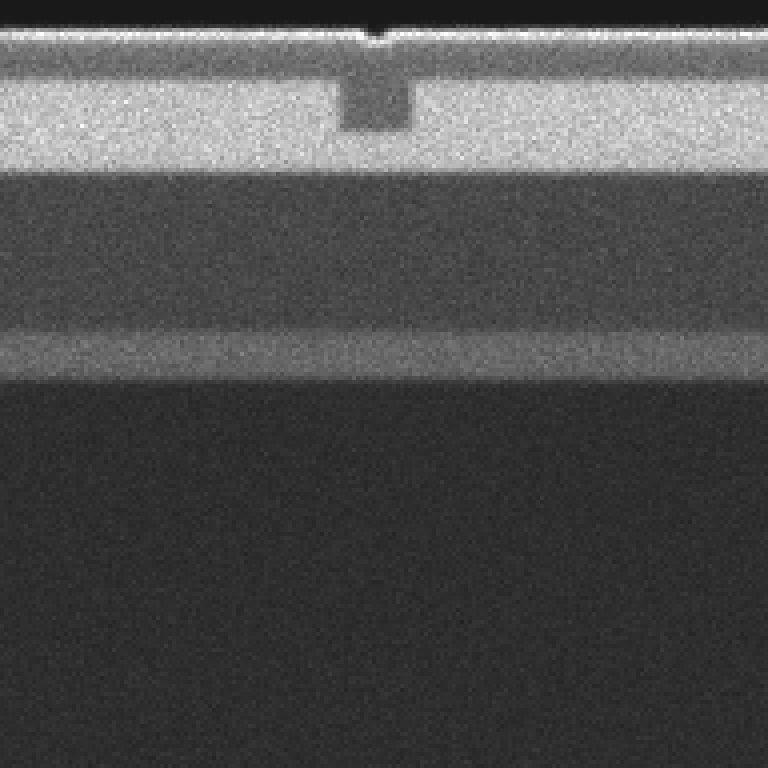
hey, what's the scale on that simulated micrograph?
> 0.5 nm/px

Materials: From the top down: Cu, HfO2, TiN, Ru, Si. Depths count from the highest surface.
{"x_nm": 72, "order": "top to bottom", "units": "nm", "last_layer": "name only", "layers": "Cu 24, HfO2 46, TiN 80, Ru 24, Si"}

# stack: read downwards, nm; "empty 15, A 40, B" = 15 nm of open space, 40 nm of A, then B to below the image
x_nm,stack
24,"Cu 24, HfO2 46, TiN 80, Ru 24, Si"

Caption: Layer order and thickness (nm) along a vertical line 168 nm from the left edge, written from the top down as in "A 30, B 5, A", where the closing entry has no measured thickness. Cu 24, HfO2 46, TiN 80, Ru 24, Si